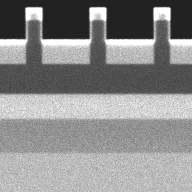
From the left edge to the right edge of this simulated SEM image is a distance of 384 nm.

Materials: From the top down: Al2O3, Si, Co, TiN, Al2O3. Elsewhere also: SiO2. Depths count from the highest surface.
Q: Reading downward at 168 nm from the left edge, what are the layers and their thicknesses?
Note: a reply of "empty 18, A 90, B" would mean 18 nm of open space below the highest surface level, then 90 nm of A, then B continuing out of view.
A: empty 64, Al2O3 48, Si 60, Co 50, TiN 68, Al2O3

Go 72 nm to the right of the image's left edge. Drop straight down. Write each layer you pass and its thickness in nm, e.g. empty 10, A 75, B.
SiO2 24, Si 148, Co 50, TiN 68, Al2O3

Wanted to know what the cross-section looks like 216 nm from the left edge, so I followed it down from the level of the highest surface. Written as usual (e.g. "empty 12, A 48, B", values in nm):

empty 64, Al2O3 48, Si 60, Co 50, TiN 68, Al2O3